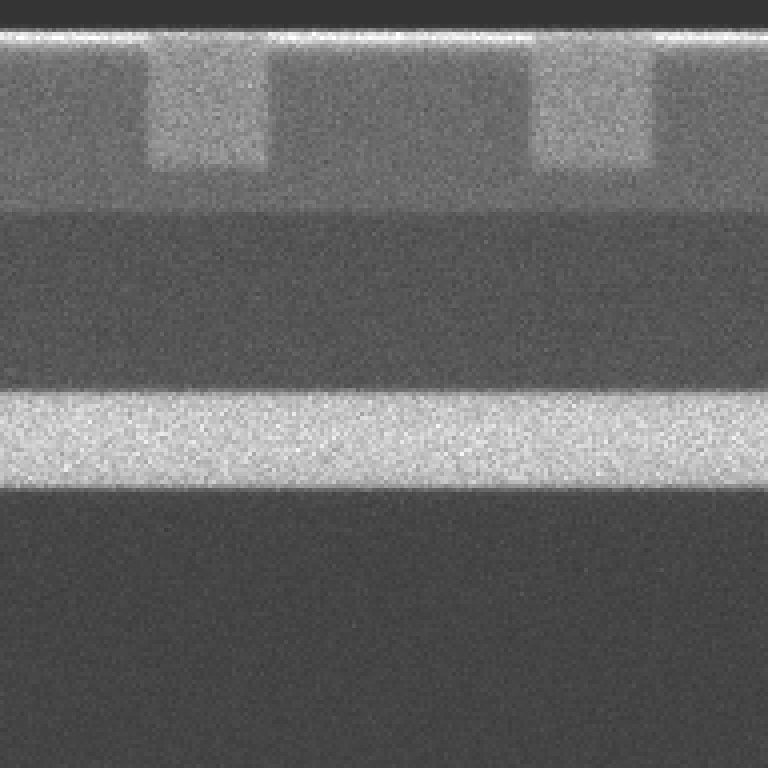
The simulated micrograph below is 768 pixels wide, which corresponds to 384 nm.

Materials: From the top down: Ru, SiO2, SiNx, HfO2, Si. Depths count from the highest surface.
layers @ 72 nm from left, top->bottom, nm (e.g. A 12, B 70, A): SiO2 90, SiNx 90, HfO2 48, Si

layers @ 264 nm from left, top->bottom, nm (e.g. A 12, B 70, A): SiO2 90, SiNx 90, HfO2 48, Si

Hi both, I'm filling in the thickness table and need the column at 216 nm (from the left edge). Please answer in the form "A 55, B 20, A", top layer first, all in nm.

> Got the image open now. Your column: SiO2 90, SiNx 90, HfO2 48, Si